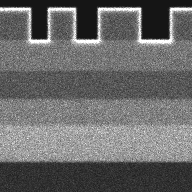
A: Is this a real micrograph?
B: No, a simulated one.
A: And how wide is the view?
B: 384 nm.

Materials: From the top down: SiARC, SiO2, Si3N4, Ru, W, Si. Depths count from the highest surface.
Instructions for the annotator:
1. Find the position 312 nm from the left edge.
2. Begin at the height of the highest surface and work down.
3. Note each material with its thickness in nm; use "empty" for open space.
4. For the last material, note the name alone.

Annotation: empty 64, SiO2 62, Si3N4 56, Ru 52, W 74, Si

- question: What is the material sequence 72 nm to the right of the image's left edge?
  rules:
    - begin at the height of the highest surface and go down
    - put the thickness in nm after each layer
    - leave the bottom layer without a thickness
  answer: empty 64, SiO2 62, Si3N4 56, Ru 52, W 74, Si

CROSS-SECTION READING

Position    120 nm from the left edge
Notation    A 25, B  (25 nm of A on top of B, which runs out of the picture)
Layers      SiARC 64, SiO2 62, Si3N4 56, Ru 52, W 74, Si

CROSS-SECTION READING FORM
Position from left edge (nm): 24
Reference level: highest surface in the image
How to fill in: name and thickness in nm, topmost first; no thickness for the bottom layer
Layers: SiARC 64, SiO2 62, Si3N4 56, Ru 52, W 74, Si